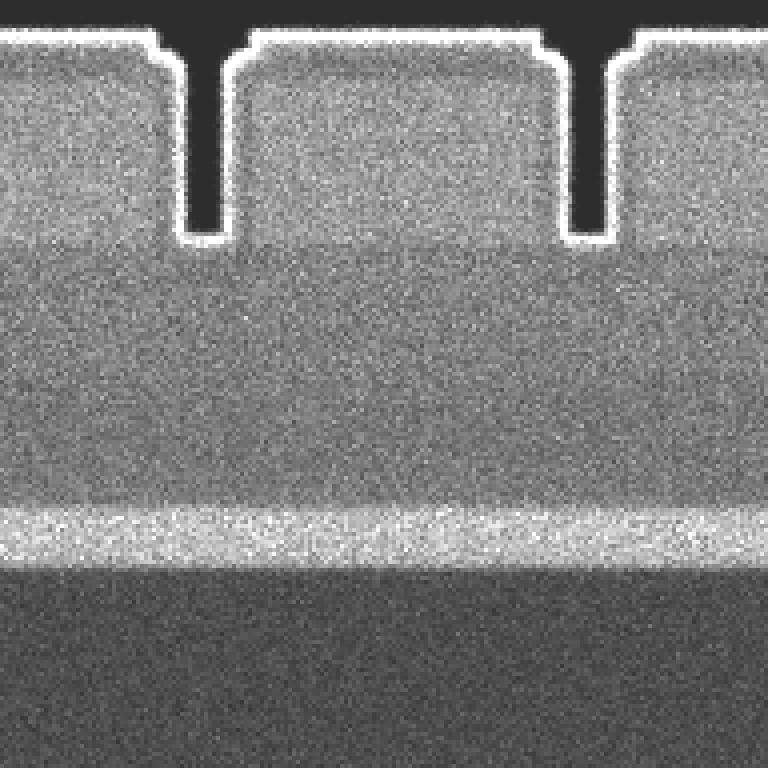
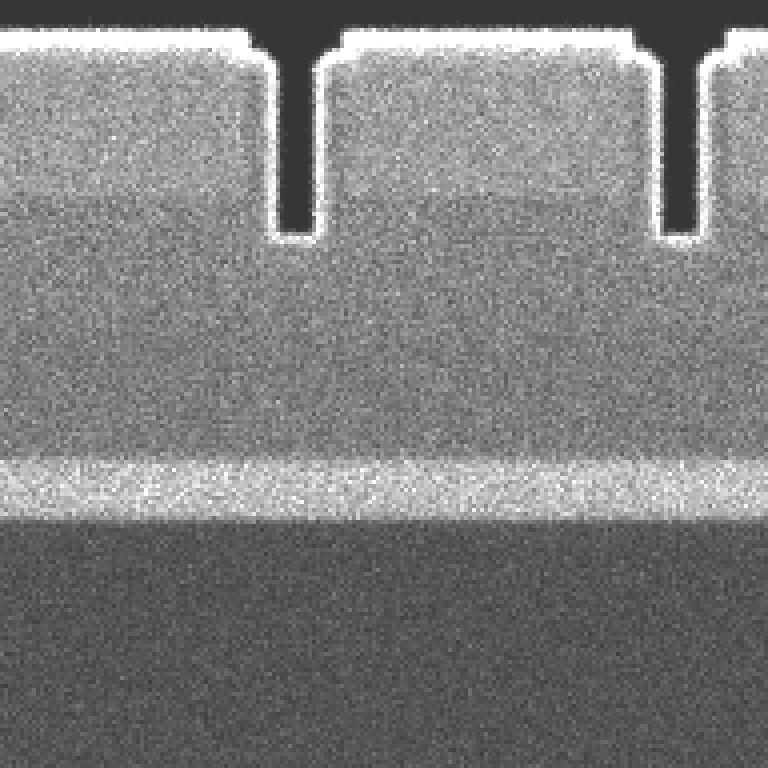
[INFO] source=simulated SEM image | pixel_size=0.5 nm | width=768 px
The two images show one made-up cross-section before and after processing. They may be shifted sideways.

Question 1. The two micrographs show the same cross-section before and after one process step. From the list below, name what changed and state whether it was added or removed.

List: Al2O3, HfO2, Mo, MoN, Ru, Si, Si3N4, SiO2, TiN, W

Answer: Si3N4, removed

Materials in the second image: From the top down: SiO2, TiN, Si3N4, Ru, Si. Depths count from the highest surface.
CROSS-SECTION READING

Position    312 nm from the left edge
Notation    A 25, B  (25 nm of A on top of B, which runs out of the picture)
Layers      SiO2 82, TiN 68, Si3N4 64, Ru 30, Si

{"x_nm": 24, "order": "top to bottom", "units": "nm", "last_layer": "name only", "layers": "SiO2 82, TiN 68, Si3N4 64, Ru 30, Si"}